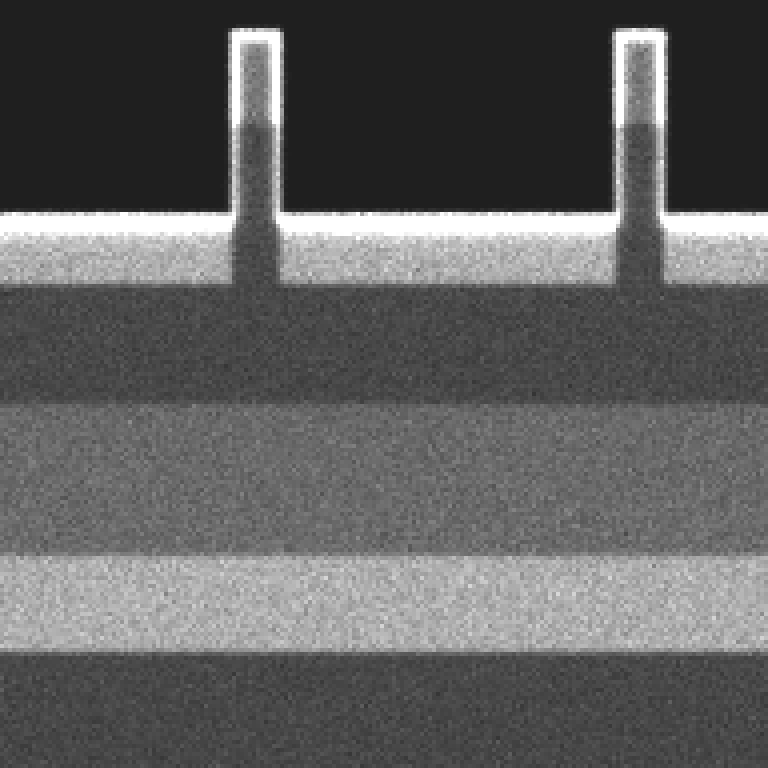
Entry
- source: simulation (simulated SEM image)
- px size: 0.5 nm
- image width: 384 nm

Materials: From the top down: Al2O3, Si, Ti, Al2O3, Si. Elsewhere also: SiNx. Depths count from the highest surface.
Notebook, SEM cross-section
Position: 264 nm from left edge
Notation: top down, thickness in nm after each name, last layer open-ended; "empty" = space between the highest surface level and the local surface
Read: empty 92, Al2O3 34, Si 60, Ti 76, Al2O3 48, Si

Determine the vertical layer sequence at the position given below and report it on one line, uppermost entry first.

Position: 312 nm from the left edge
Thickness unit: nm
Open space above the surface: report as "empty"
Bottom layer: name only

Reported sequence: SiNx 46, Si 140, Ti 76, Al2O3 48, Si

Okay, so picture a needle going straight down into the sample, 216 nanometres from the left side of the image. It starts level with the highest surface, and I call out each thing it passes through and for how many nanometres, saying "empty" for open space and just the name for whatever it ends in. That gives empty 92, Al2O3 34, Si 60, Ti 76, Al2O3 48, Si